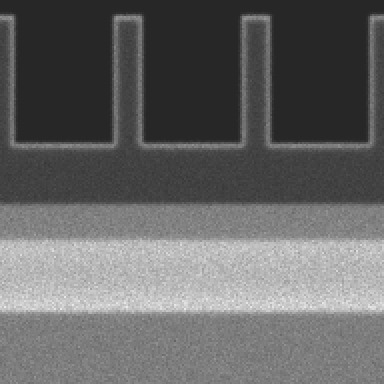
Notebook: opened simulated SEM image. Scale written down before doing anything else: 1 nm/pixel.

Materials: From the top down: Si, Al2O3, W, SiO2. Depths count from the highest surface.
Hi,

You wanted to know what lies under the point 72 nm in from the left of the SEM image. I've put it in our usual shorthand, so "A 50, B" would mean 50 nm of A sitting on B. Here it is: empty 128, Si 60, Al2O3 36, W 72, SiO2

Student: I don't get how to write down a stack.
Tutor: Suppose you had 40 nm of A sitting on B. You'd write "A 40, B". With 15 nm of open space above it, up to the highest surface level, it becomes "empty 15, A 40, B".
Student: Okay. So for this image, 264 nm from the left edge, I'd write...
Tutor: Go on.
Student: Si 188, Al2O3 36, W 72, SiO2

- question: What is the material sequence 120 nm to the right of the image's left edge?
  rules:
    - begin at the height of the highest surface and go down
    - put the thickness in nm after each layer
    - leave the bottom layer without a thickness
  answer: Si 188, Al2O3 36, W 72, SiO2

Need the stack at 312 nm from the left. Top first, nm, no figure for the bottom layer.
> empty 128, Si 60, Al2O3 36, W 72, SiO2